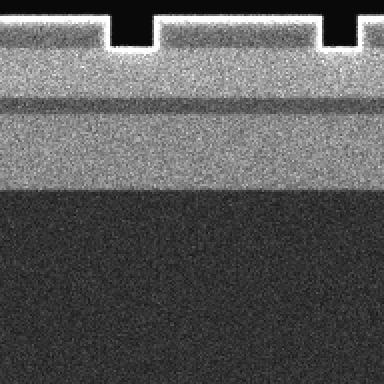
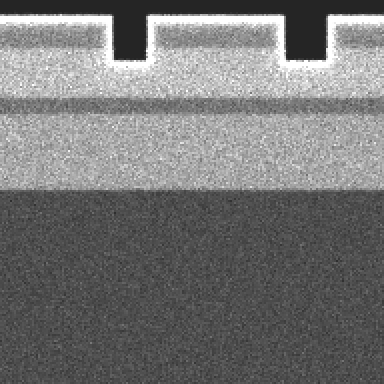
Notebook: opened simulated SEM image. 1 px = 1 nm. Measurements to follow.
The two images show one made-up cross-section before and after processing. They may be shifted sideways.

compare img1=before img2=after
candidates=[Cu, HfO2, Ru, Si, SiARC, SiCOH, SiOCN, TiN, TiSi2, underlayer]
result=removed:Ru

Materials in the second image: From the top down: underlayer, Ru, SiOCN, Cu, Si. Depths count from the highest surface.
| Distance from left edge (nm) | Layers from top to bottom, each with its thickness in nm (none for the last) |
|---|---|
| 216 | underlayer 32, Ru 50, SiOCN 16, Cu 76, Si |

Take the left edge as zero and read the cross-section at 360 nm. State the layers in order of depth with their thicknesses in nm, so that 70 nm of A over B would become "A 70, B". underlayer 32, Ru 50, SiOCN 16, Cu 76, Si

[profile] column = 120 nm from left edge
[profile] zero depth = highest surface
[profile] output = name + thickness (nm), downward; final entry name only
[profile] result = empty 46, Ru 36, SiOCN 16, Cu 76, Si